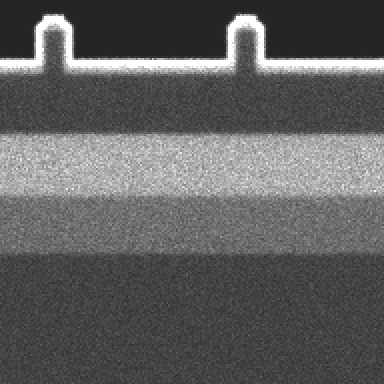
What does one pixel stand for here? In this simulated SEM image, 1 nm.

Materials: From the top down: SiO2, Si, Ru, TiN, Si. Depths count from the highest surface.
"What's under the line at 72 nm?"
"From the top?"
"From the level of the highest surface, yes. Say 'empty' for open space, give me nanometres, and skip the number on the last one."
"empty 44, SiO2 14, Si 60, Ru 62, TiN 58, Si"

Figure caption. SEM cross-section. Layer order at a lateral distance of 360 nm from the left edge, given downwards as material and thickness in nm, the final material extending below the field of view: empty 44, SiO2 14, Si 60, Ru 62, TiN 58, Si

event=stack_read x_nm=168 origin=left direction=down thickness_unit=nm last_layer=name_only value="empty 44, SiO2 14, Si 60, Ru 62, TiN 58, Si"